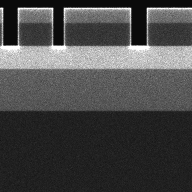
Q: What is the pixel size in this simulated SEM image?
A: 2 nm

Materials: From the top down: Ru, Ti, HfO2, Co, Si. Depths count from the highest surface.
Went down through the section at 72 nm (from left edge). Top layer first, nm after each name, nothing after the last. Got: Ru 30, Ti 46, HfO2 46, Co 84, Si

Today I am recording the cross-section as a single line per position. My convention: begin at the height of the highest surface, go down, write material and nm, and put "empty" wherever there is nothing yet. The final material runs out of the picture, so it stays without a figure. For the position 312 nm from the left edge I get Ru 30, Ti 46, HfO2 46, Co 84, Si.